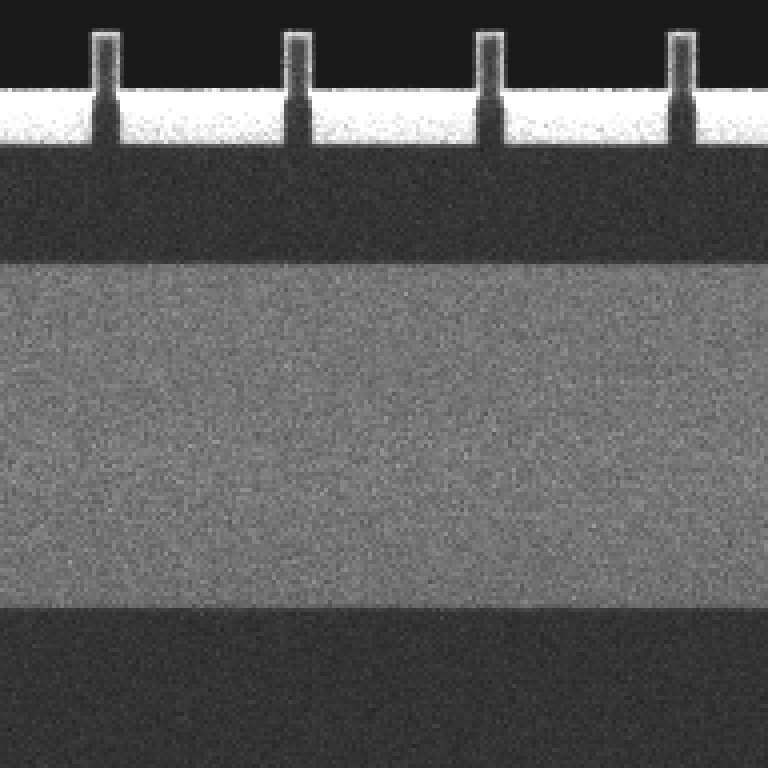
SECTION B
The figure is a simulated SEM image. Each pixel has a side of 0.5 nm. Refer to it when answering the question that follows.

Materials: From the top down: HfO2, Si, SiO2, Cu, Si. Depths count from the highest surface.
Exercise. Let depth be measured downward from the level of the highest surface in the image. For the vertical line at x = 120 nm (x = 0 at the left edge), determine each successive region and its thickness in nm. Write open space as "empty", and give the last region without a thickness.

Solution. empty 30, HfO2 26, Si 60, SiO2 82, Cu 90, Si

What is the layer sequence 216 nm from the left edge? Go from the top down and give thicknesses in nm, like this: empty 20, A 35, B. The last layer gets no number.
empty 30, HfO2 26, Si 60, SiO2 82, Cu 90, Si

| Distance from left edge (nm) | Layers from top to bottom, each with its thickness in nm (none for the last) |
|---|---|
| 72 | empty 30, HfO2 26, Si 60, SiO2 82, Cu 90, Si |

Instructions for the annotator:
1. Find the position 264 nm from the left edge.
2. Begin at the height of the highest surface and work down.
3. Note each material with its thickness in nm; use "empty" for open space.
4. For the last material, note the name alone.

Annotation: empty 30, HfO2 26, Si 60, SiO2 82, Cu 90, Si